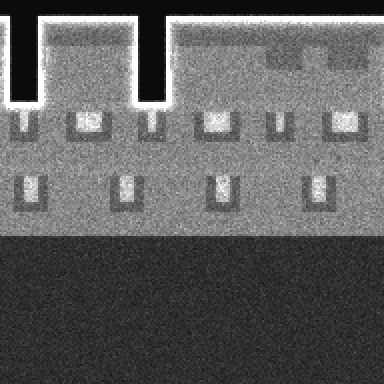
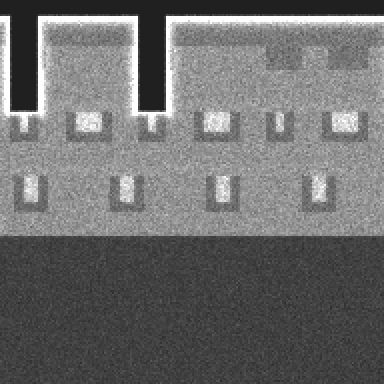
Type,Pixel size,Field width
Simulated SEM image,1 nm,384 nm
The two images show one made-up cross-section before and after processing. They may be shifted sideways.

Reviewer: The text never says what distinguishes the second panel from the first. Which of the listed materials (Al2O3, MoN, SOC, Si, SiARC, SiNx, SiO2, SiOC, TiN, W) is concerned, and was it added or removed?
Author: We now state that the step removed Al2O3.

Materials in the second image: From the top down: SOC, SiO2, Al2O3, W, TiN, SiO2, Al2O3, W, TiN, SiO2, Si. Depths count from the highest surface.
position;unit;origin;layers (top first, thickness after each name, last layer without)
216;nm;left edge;SOC 30, SiO2 56, Al2O3 10, W 20, TiN 10, SiO2 22, Al2O3 12, W 26, TiN 10, SiO2 24, Si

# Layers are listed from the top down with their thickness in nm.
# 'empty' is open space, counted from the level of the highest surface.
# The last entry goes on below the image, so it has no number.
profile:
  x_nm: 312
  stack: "SOC 30, SiO2 56, Al2O3 10, SiO2 52, Al2O3 12, W 26, TiN 10, SiO2 24, Si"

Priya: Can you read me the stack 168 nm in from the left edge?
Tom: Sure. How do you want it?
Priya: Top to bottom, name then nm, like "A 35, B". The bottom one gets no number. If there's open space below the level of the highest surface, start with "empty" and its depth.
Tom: SOC 54, SiO2 32, Al2O3 10, SiO2 52, Al2O3 12, SiO2 60, Si